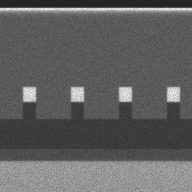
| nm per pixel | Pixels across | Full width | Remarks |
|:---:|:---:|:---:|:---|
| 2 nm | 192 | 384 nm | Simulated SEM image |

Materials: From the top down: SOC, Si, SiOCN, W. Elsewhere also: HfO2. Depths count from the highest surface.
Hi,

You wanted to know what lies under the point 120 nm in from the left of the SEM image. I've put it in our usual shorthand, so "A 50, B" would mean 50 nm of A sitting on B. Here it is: SOC 222, Si 60, SiOCN 24, W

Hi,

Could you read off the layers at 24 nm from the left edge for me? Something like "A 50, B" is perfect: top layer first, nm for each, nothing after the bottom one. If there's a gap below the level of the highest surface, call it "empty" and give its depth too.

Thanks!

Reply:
SOC 222, Si 60, SiOCN 24, W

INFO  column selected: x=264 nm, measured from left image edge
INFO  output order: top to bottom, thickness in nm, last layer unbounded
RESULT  SOC 222, Si 60, SiOCN 24, W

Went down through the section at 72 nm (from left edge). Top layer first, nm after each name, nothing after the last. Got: SOC 222, Si 60, SiOCN 24, W